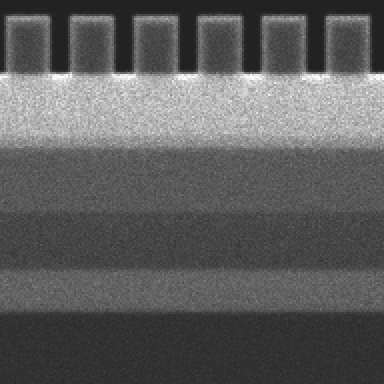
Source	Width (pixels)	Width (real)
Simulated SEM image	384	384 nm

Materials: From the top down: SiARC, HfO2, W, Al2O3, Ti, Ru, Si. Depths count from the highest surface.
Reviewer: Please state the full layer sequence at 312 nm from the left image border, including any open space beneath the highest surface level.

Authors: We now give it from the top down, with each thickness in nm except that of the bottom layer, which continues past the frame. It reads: empty 58, HfO2 62, W 12, Al2O3 64, Ti 58, Ru 42, Si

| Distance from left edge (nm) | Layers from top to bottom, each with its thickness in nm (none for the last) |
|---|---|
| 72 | SiARC 58, HfO2 62, W 12, Al2O3 64, Ti 58, Ru 42, Si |